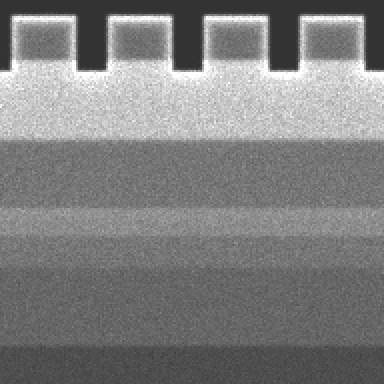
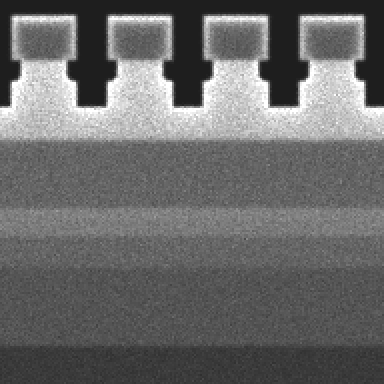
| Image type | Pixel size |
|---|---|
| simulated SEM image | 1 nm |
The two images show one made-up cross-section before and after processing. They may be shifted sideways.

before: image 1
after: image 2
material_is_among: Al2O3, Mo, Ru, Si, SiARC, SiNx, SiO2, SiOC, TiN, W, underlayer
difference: W, removed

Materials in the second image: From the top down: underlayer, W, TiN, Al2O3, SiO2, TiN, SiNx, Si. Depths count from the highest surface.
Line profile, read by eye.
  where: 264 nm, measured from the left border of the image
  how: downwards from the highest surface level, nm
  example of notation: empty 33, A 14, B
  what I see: underlayer 44, empty 22, W 58, TiN 68, Al2O3 12, SiO2 16, TiN 32, SiNx 78, Si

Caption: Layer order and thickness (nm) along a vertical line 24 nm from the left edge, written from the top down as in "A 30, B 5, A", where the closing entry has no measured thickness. underlayer 44, W 80, TiN 68, Al2O3 12, SiO2 16, TiN 32, SiNx 78, Si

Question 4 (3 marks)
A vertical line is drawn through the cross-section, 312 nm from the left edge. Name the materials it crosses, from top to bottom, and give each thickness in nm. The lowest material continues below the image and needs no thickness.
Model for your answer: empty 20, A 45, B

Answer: underlayer 44, W 80, TiN 68, Al2O3 12, SiO2 16, TiN 32, SiNx 78, Si